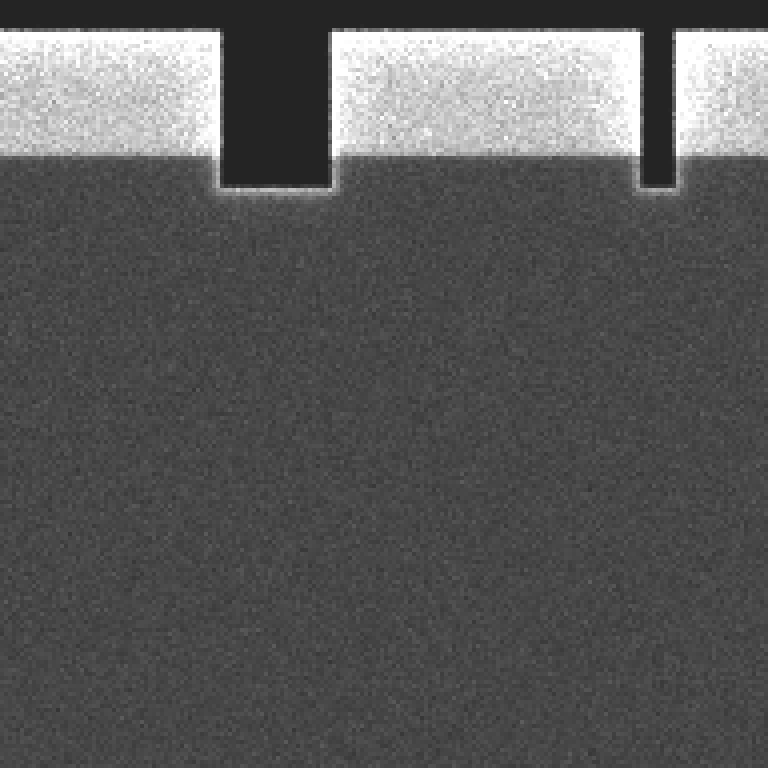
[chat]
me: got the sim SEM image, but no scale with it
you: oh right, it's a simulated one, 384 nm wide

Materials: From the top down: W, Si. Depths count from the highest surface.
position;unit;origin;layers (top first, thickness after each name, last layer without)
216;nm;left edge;W 62, Si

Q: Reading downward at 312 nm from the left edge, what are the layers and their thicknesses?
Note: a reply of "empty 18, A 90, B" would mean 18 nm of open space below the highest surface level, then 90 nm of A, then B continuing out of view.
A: W 62, Si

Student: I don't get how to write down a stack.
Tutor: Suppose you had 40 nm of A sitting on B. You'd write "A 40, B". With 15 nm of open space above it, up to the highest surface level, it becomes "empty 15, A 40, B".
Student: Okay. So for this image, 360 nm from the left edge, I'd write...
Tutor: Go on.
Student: W 62, Si